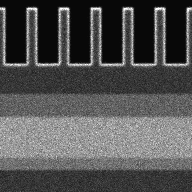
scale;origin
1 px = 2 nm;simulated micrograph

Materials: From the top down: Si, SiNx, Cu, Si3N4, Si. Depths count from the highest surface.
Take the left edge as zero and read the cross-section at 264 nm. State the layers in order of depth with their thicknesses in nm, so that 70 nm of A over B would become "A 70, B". Si 172, SiNx 46, Cu 82, Si3N4 24, Si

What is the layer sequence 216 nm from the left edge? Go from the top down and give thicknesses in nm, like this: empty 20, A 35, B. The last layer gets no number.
empty 112, Si 60, SiNx 46, Cu 82, Si3N4 24, Si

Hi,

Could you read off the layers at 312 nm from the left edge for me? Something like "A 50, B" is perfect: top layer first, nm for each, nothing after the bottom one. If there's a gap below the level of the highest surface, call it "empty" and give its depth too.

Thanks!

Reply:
Si 172, SiNx 46, Cu 82, Si3N4 24, Si